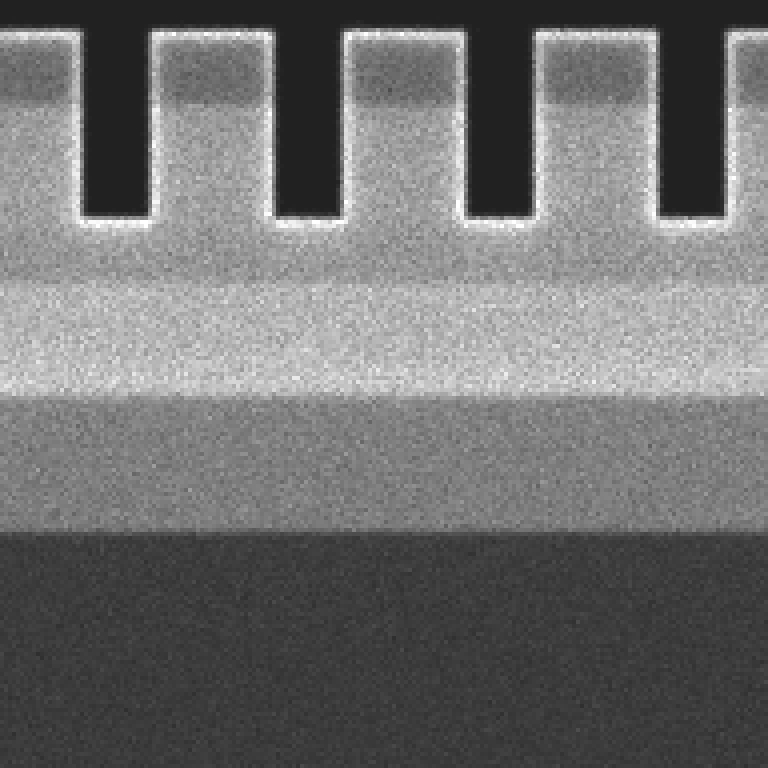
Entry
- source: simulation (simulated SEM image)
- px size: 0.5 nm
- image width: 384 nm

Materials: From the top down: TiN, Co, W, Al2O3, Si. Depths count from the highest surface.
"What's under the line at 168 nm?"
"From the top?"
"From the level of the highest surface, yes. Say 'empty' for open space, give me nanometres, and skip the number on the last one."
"empty 94, Co 32, W 56, Al2O3 68, Si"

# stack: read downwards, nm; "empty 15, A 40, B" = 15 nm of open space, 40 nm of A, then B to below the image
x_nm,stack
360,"empty 94, Co 32, W 56, Al2O3 68, Si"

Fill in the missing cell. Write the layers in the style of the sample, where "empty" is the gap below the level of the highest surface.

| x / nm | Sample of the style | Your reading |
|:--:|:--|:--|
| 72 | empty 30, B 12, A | empty 94, Co 32, W 56, Al2O3 68, Si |